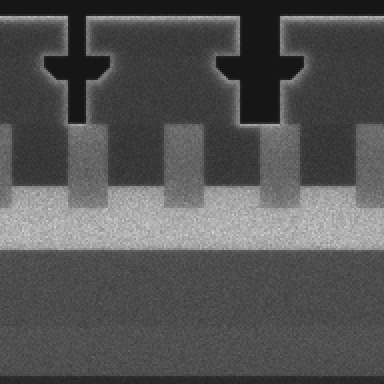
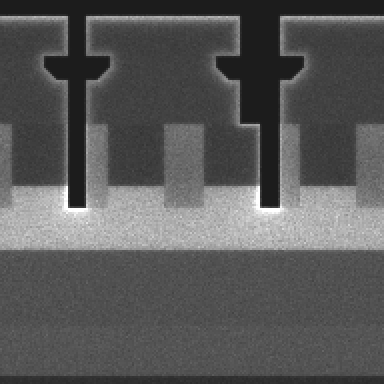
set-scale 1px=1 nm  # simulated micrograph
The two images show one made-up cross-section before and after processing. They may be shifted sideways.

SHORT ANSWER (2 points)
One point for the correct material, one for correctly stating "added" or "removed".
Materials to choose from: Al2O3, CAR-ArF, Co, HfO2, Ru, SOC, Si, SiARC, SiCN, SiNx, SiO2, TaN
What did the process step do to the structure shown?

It removed Ru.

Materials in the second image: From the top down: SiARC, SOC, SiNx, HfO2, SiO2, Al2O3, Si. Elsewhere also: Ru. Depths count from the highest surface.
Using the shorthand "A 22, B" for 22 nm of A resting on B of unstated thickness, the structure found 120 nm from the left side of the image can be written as SiARC 40, SOC 68, SiNx 62, HfO2 64, SiO2 76, Al2O3 50, Si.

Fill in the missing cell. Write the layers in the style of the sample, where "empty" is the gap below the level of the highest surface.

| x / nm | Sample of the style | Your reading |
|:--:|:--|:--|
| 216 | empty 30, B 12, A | SiARC 40, empty 12, SOC 56, SiNx 62, HfO2 64, SiO2 76, Al2O3 50, Si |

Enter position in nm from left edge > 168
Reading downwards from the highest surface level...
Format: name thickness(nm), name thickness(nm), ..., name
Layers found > SiARC 40, SOC 68, Ru 84, HfO2 42, SiO2 76, Al2O3 50, Si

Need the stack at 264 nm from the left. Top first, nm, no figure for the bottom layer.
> empty 192, HfO2 42, SiO2 76, Al2O3 50, Si